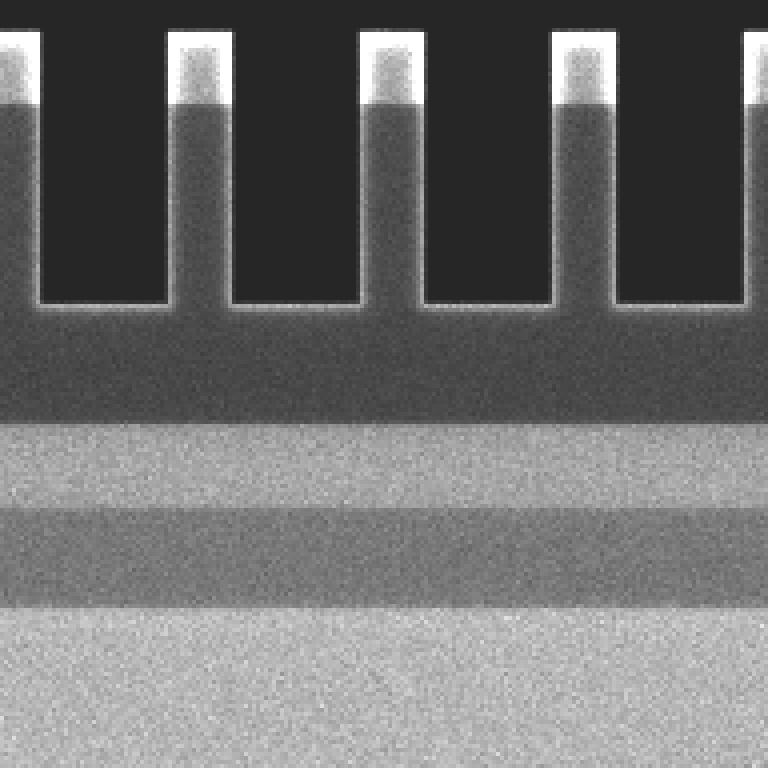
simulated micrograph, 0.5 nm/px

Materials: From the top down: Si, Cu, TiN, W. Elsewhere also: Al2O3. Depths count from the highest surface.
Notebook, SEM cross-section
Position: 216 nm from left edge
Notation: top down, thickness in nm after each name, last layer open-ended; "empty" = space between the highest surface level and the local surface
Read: empty 136, Si 60, Cu 42, TiN 50, W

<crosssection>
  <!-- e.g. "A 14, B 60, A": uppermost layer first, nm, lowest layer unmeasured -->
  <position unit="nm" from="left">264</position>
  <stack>empty 136, Si 60, Cu 42, TiN 50, W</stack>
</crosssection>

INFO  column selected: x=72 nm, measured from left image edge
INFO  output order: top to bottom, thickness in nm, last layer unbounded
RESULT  empty 136, Si 60, Cu 42, TiN 50, W